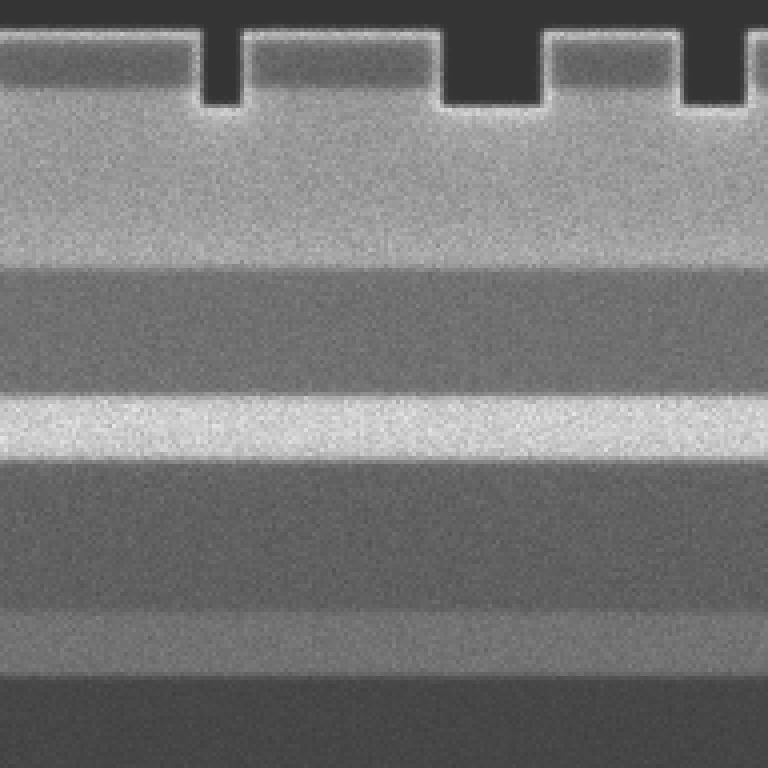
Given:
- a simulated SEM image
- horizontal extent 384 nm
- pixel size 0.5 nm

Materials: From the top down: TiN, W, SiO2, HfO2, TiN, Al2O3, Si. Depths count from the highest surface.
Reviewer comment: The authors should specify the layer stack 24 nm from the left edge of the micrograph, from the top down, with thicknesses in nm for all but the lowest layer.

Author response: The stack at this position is TiN 28, W 90, SiO2 64, HfO2 32, TiN 76, Al2O3 32, Si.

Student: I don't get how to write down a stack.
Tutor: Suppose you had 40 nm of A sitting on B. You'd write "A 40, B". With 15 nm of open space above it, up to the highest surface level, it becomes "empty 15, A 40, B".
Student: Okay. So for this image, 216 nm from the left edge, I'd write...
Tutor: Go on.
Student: TiN 28, W 90, SiO2 64, HfO2 32, TiN 76, Al2O3 32, Si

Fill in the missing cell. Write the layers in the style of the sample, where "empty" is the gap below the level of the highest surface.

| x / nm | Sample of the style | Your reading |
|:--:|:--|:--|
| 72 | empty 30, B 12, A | TiN 28, W 90, SiO2 64, HfO2 32, TiN 76, Al2O3 32, Si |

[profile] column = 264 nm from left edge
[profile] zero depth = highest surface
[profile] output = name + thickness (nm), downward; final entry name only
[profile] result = empty 38, W 80, SiO2 64, HfO2 32, TiN 76, Al2O3 32, Si